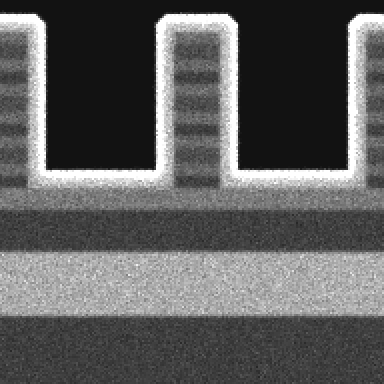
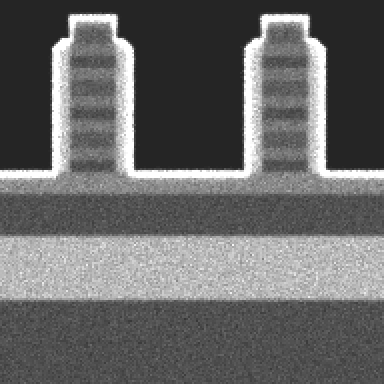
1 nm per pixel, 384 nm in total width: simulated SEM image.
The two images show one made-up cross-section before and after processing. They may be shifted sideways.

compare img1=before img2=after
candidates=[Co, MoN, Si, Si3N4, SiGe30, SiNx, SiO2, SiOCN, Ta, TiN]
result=removed:Co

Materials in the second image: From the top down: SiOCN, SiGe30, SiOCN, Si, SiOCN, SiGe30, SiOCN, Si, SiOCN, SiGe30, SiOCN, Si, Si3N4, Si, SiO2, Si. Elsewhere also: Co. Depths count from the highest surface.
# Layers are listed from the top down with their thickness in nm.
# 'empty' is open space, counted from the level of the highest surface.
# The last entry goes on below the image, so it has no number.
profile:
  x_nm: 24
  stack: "empty 156, Si3N4 22, Si 42, SiO2 64, Si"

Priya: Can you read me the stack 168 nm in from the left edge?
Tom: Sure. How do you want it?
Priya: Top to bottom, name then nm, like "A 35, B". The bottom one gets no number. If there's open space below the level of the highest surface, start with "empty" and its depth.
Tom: empty 156, Si3N4 22, Si 42, SiO2 64, Si